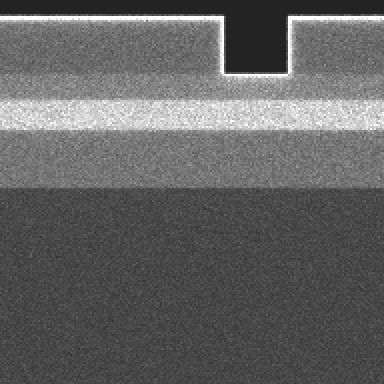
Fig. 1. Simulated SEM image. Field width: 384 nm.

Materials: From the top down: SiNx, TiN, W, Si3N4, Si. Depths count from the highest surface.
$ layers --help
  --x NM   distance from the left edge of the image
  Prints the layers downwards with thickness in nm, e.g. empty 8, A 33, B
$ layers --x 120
SiNx 58, TiN 26, W 30, Si3N4 58, Si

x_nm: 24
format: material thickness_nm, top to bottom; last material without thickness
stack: SiNx 58, TiN 26, W 30, Si3N4 58, Si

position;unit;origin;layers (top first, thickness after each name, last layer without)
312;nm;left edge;SiNx 58, TiN 26, W 30, Si3N4 58, Si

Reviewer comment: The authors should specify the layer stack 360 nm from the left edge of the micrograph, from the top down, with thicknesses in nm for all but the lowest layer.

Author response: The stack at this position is SiNx 58, TiN 26, W 30, Si3N4 58, Si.